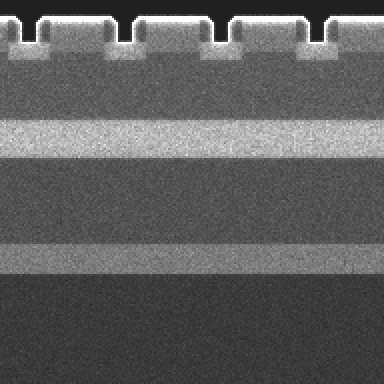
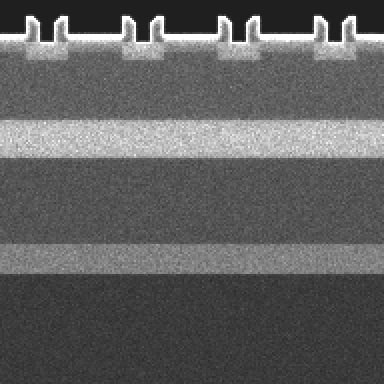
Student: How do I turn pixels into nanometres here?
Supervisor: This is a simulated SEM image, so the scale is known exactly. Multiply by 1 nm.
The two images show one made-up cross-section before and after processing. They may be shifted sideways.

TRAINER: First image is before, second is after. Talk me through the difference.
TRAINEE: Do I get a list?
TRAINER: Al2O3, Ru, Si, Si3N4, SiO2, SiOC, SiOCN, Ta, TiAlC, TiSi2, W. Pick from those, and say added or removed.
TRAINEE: removed: SiO2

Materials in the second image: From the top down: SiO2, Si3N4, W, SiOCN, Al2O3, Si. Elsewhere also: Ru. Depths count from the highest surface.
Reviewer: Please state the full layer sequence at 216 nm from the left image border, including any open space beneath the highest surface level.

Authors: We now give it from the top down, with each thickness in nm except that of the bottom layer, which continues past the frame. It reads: empty 18, SiO2 18, Si3N4 68, W 38, SiOCN 86, Al2O3 30, Si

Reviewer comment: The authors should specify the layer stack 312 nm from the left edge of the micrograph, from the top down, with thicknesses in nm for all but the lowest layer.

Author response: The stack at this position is empty 18, SiO2 18, Si3N4 68, W 38, SiOCN 86, Al2O3 30, Si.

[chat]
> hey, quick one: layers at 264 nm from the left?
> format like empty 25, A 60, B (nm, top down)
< empty 18, SiO2 18, Si3N4 68, W 38, SiOCN 86, Al2O3 30, Si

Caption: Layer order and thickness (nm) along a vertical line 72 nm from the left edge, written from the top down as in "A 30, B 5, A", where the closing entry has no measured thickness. empty 18, SiO2 18, Si3N4 68, W 38, SiOCN 86, Al2O3 30, Si